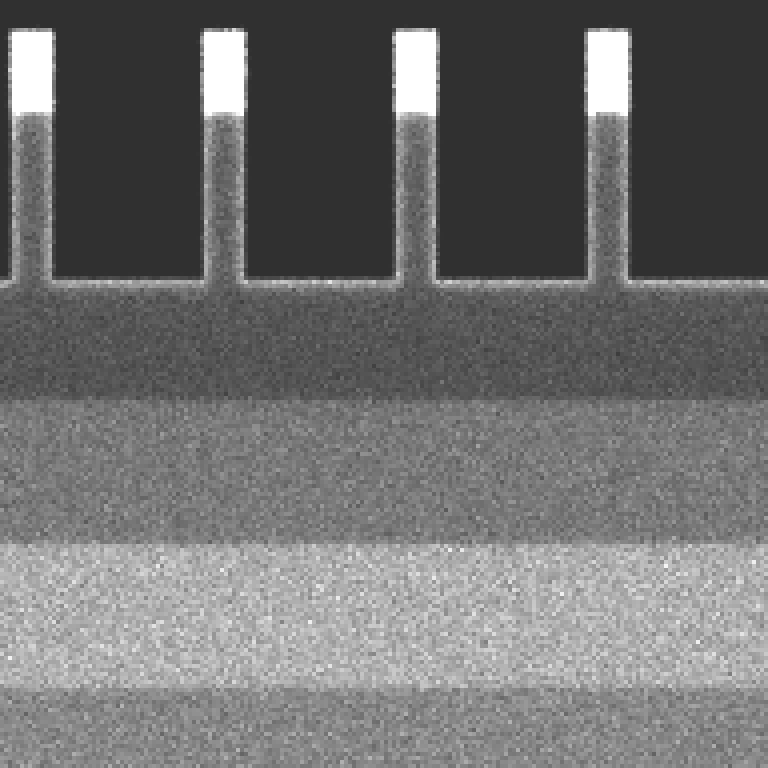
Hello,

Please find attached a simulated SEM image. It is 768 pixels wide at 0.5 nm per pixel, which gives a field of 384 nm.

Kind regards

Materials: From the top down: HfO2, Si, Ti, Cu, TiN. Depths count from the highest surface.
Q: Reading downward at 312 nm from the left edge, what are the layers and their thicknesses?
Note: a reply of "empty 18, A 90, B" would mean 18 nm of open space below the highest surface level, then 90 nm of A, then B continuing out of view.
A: HfO2 40, Si 144, Ti 72, Cu 72, TiN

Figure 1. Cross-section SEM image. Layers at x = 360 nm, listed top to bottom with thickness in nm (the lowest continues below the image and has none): empty 124, Si 60, Ti 72, Cu 72, TiN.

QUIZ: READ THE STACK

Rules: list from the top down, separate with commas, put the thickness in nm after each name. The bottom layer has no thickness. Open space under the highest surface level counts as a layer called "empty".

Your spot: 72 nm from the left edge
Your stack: empty 124, Si 60, Ti 72, Cu 72, TiN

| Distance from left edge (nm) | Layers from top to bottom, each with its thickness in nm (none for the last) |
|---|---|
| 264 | empty 124, Si 60, Ti 72, Cu 72, TiN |